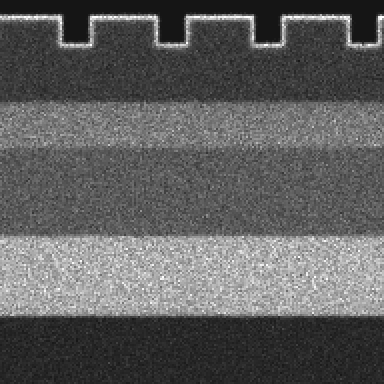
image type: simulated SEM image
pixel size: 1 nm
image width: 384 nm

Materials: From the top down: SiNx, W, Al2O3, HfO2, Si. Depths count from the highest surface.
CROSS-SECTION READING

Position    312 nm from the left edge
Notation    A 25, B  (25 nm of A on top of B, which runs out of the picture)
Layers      SiNx 86, W 46, Al2O3 88, HfO2 80, Si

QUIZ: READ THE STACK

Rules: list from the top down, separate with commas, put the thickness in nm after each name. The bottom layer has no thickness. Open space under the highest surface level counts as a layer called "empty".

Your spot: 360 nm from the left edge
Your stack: empty 28, SiNx 58, W 46, Al2O3 88, HfO2 80, Si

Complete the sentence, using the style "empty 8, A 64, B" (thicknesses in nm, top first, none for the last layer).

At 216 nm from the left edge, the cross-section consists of SiNx 86, W 46, Al2O3 88, HfO2 80, Si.